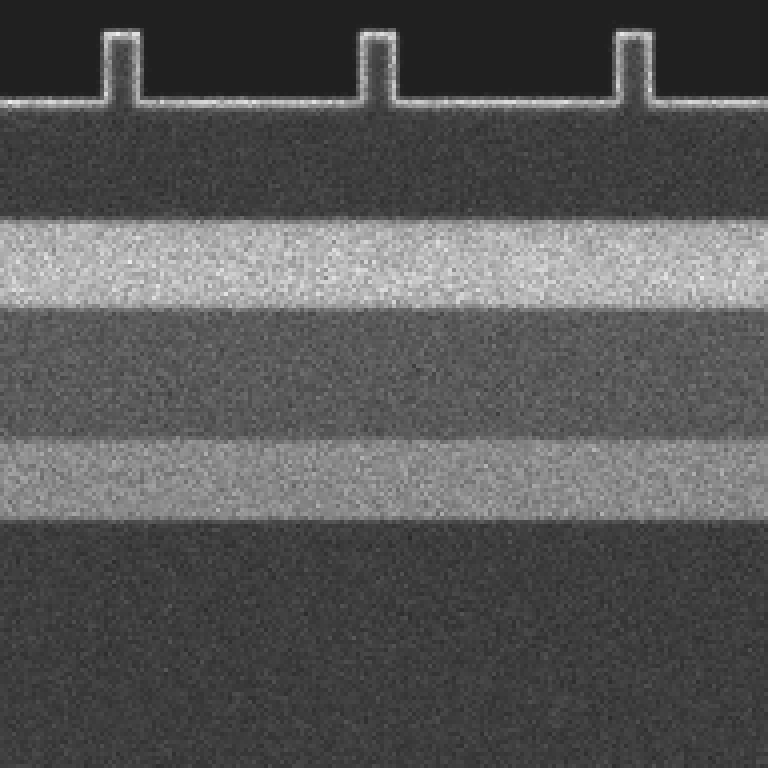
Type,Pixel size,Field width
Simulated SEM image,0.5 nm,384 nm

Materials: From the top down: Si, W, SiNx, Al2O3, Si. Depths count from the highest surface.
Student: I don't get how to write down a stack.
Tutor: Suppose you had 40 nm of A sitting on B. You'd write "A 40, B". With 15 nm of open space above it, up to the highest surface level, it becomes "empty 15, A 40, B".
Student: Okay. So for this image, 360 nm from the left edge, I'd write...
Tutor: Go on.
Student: empty 34, Si 60, W 44, SiNx 66, Al2O3 40, Si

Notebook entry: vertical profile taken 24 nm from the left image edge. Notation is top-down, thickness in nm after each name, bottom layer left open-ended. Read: empty 34, Si 60, W 44, SiNx 66, Al2O3 40, Si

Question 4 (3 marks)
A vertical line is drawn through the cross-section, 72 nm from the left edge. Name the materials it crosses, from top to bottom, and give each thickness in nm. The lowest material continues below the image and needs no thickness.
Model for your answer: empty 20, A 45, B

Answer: empty 34, Si 60, W 44, SiNx 66, Al2O3 40, Si